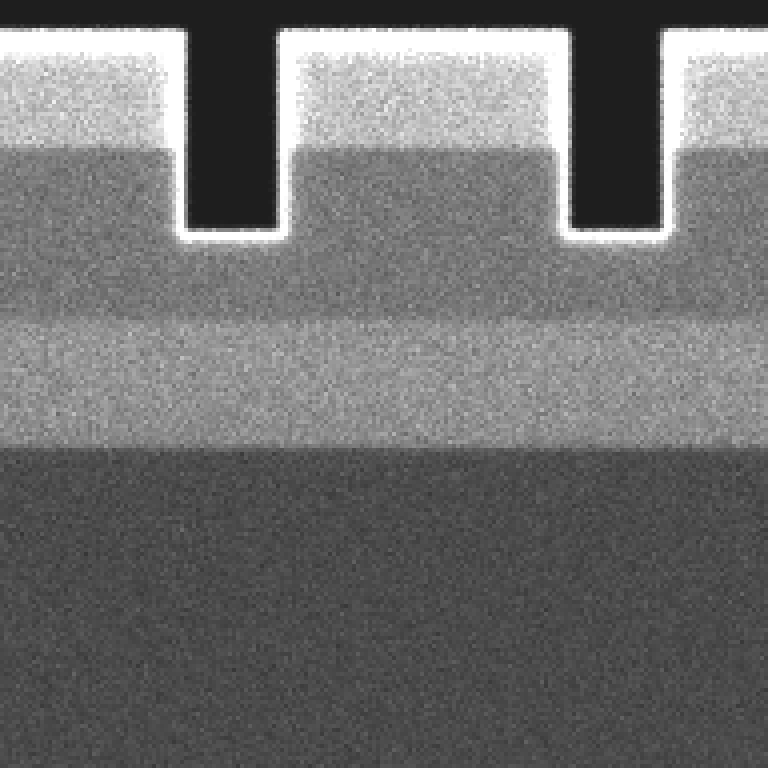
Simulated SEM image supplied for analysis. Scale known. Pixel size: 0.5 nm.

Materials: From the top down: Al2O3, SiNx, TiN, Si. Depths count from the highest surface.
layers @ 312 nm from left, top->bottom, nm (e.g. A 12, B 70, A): empty 100, SiNx 44, TiN 64, Si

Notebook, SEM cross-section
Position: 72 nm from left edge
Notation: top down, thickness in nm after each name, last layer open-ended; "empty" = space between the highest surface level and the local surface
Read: Al2O3 58, SiNx 86, TiN 64, Si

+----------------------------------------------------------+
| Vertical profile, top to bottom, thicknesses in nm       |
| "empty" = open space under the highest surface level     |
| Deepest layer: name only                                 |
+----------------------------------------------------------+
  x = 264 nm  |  Al2O3 58, SiNx 86, TiN 64, Si